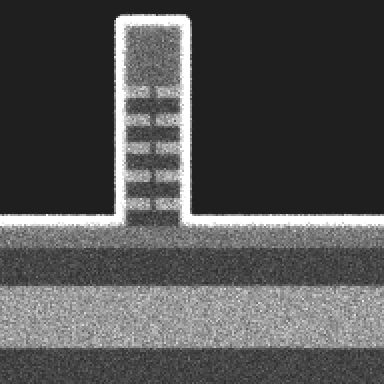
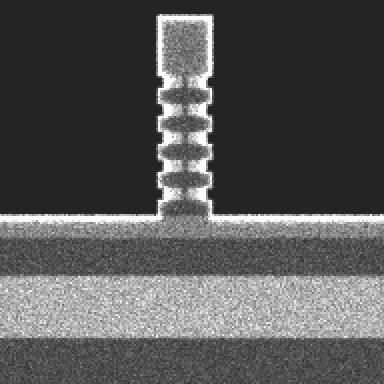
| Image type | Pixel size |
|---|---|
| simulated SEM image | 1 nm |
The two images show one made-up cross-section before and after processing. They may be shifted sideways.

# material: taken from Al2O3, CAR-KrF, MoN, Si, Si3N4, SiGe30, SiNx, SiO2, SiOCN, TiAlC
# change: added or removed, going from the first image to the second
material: Al2O3
change: removed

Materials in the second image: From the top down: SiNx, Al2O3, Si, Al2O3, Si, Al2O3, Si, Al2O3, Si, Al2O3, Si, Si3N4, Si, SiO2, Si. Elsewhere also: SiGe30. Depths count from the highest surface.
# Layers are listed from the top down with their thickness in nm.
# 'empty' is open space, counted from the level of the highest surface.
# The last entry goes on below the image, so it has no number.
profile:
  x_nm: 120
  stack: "empty 200, Si3N4 22, Si 38, SiO2 62, Si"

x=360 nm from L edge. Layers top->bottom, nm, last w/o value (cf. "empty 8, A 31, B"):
empty 200, Si3N4 22, Si 38, SiO2 62, Si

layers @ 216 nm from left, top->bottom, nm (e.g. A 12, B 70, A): empty 200, Si3N4 22, Si 38, SiO2 62, Si